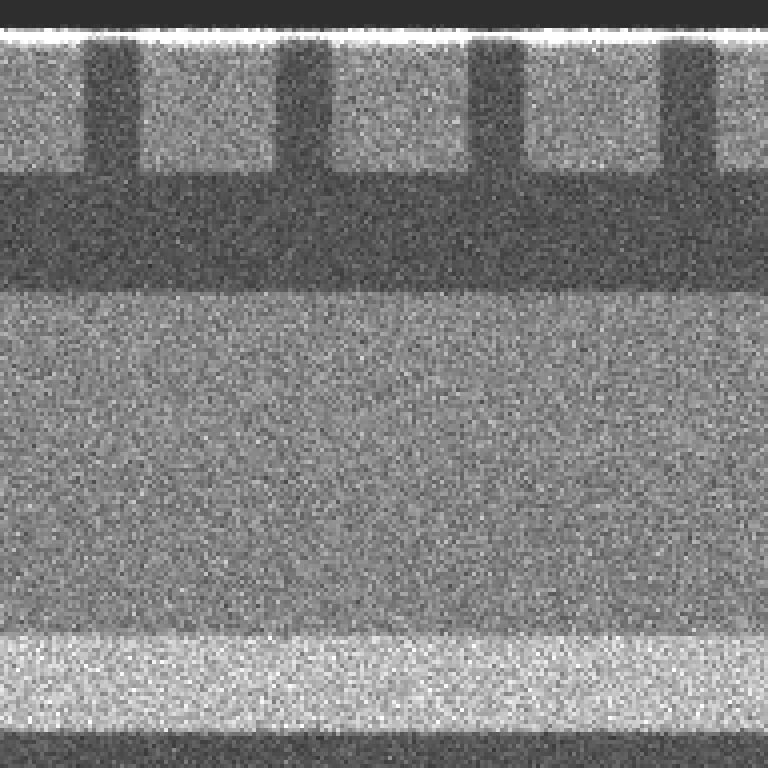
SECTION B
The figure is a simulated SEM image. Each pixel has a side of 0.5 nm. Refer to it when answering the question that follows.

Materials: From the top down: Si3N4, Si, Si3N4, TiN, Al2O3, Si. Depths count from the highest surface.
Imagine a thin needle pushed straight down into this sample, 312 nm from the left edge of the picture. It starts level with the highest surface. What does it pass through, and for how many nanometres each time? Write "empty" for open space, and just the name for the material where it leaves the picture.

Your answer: Si3N4 70, Si 60, Si3N4 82, TiN 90, Al2O3 48, Si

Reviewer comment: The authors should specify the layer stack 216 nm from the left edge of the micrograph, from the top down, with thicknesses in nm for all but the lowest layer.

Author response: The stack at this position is Si3N4 70, Si 60, Si3N4 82, TiN 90, Al2O3 48, Si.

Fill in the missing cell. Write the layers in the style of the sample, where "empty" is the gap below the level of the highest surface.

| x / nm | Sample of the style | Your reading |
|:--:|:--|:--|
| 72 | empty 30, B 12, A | Si3N4 70, Si 60, Si3N4 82, TiN 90, Al2O3 48, Si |